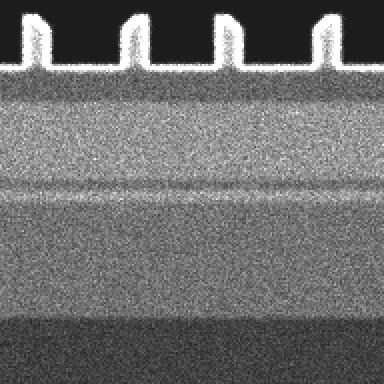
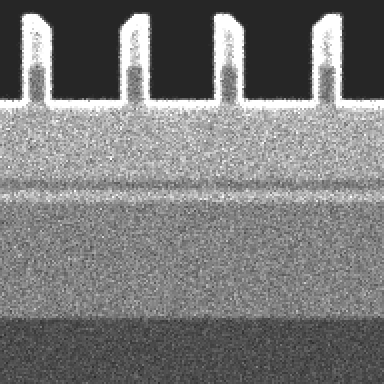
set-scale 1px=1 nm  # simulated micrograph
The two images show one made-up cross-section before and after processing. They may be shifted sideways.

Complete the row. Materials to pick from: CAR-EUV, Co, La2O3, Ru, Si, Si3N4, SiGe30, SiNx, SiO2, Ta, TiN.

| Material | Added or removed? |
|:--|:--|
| SiNx | removed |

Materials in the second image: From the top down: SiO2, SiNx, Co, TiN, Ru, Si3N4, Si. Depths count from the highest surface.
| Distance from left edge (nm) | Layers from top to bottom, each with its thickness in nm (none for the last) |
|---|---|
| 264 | empty 86, Co 78, TiN 10, Ru 12, Si3N4 116, Si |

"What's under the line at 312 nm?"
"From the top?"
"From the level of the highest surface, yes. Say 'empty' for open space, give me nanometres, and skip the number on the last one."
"empty 86, Co 78, TiN 10, Ru 12, Si3N4 116, Si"